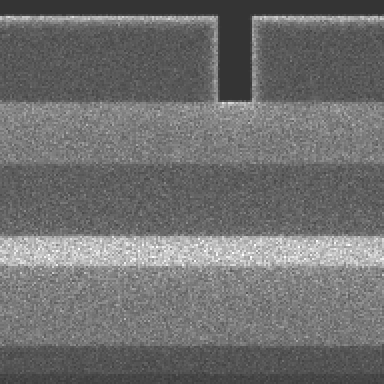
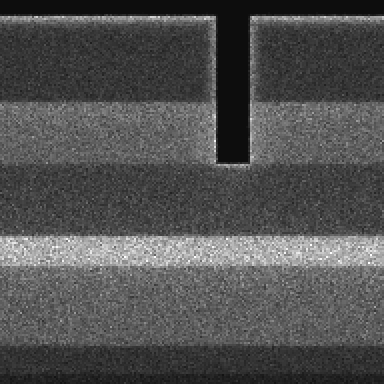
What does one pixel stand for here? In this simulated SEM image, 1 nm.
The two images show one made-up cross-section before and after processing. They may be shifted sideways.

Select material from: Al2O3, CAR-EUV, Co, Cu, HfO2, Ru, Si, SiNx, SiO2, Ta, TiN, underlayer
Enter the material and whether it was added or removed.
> Ru / removed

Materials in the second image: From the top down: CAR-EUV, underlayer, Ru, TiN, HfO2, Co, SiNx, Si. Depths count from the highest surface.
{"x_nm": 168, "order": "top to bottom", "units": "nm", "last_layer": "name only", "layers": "CAR-EUV 32, underlayer 54, Ru 62, TiN 72, HfO2 30, Co 80, SiNx 28, Si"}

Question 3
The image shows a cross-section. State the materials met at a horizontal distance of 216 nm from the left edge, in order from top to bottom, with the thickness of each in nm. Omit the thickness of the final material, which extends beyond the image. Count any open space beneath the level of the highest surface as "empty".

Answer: empty 148, TiN 72, HfO2 30, Co 80, SiNx 28, Si